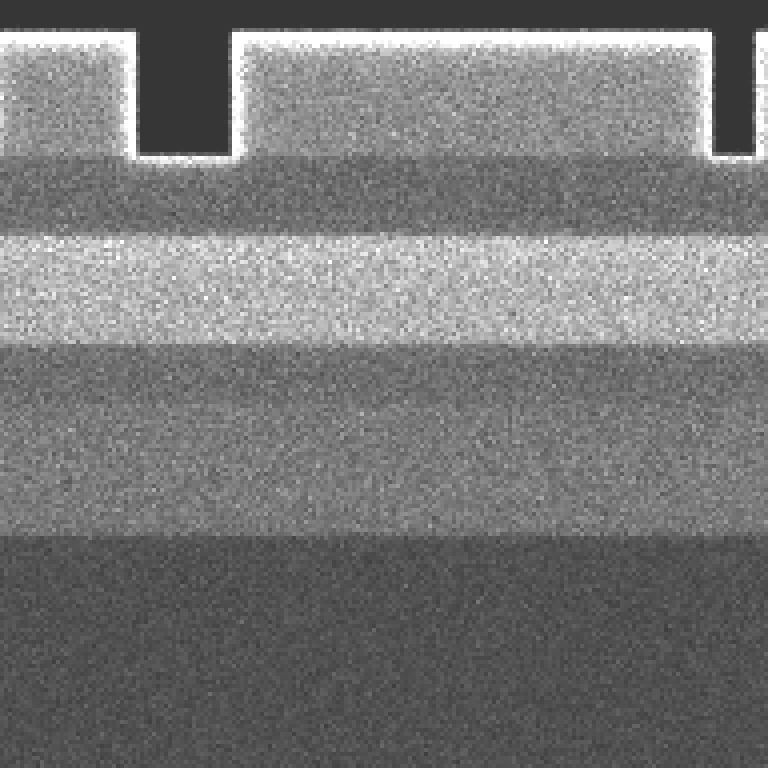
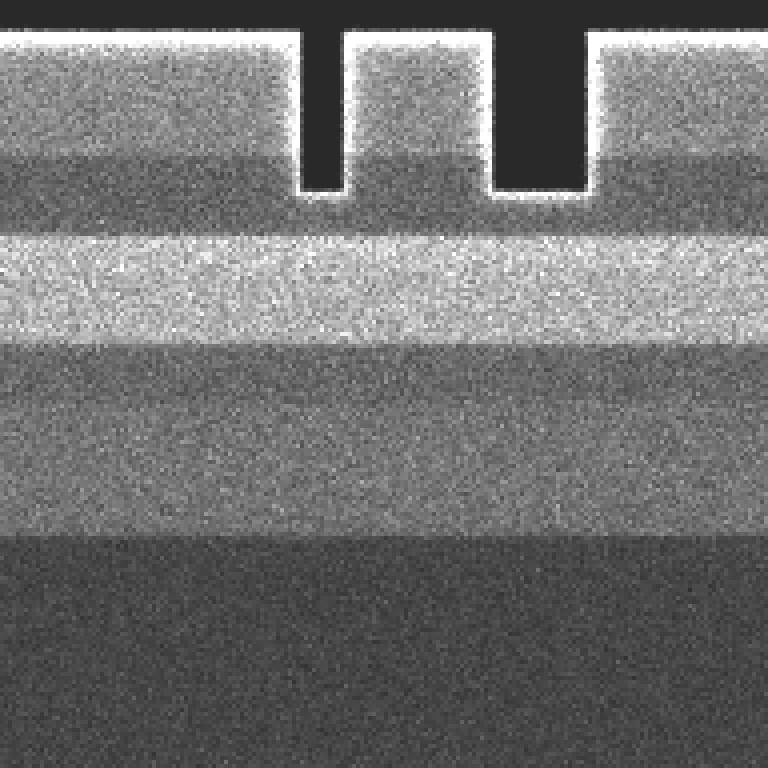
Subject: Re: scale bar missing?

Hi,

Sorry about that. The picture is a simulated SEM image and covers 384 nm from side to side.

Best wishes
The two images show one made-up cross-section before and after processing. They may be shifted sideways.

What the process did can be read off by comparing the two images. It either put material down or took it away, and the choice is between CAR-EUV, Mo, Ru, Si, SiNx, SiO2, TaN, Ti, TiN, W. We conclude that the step removed SiNx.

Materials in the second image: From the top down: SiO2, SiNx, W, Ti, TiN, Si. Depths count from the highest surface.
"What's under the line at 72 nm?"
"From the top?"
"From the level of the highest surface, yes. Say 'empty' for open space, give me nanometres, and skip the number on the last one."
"SiO2 62, SiNx 40, W 54, Ti 30, TiN 66, Si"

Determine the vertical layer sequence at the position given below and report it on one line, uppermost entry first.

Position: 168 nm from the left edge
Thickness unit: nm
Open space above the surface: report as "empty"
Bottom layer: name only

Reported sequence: empty 80, SiNx 22, W 54, Ti 30, TiN 66, Si